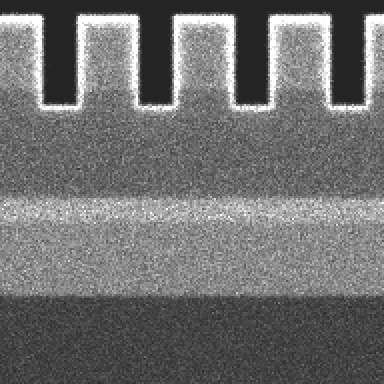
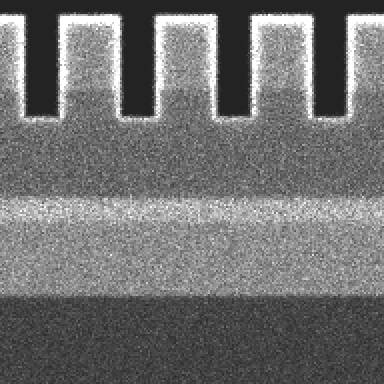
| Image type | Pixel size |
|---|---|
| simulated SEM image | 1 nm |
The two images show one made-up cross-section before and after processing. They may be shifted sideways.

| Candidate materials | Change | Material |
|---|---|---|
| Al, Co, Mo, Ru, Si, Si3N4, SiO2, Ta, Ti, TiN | removed | Si3N4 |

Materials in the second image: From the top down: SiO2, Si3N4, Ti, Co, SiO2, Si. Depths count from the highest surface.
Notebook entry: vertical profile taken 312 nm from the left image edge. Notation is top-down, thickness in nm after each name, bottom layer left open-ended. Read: empty 102, Ti 80, Co 24, SiO2 74, Si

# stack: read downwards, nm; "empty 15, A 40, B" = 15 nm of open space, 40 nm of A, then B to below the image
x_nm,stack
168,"SiO2 74, Si3N4 28, Ti 80, Co 24, SiO2 74, Si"